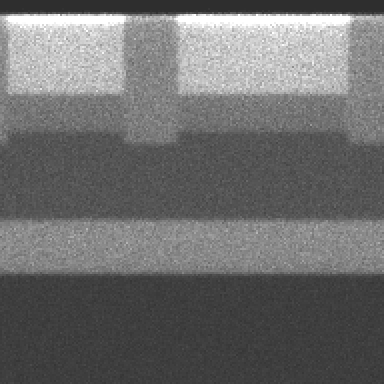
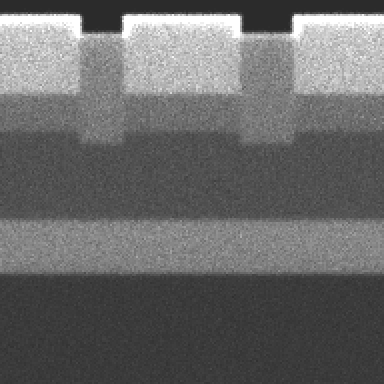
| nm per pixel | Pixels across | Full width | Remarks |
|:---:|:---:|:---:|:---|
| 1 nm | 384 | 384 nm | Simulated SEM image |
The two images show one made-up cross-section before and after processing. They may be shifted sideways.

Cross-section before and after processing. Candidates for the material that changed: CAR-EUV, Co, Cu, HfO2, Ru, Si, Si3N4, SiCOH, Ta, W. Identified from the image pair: Ru (removed).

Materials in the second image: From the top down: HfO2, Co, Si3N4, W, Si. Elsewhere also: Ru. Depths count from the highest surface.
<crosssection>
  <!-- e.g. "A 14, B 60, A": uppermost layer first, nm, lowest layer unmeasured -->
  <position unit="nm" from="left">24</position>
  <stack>HfO2 78, Co 38, Si3N4 88, W 54, Si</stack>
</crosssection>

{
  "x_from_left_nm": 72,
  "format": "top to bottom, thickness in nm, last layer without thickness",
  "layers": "HfO2 78, Co 38, Si3N4 88, W 54, Si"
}